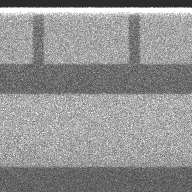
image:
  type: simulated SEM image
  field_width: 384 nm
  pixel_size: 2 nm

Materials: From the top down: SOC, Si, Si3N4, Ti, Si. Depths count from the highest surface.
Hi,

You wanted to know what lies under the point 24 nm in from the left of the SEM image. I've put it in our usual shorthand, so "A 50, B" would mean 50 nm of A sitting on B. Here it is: SOC 112, Si 60, Si3N4 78, Ti 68, Si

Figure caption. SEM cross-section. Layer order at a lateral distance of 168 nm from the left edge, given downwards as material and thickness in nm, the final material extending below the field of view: SOC 112, Si 60, Si3N4 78, Ti 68, Si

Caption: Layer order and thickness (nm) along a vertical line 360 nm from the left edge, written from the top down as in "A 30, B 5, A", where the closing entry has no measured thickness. SOC 112, Si 60, Si3N4 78, Ti 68, Si